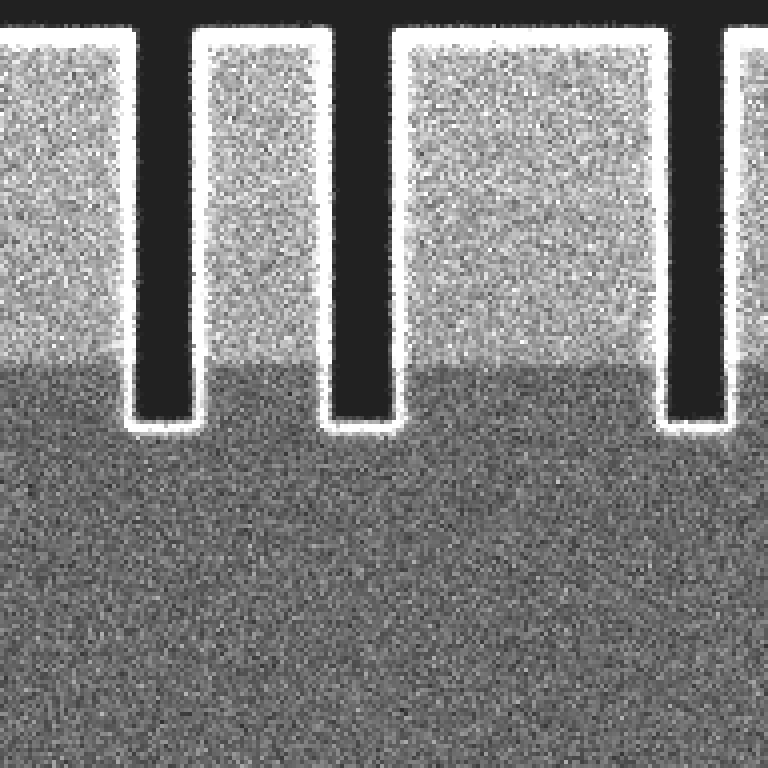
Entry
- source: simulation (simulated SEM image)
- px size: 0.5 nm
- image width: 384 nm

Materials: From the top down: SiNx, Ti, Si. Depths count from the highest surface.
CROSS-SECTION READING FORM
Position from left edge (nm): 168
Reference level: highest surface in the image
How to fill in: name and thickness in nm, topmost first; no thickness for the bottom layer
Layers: empty 196, Si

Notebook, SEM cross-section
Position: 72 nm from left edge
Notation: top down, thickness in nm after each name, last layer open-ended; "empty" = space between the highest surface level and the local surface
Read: empty 196, Si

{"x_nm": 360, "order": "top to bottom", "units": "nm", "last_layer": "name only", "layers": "empty 196, Si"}